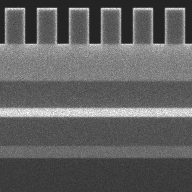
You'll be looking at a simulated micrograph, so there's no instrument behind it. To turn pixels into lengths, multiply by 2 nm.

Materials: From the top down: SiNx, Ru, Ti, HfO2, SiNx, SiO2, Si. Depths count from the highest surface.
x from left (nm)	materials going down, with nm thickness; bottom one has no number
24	SiNx 72, Ru 74, Ti 54, HfO2 18, SiNx 58, SiO2 24, Si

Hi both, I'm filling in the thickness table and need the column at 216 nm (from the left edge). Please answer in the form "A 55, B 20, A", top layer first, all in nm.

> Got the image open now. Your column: SiNx 72, Ru 74, Ti 54, HfO2 18, SiNx 58, SiO2 24, Si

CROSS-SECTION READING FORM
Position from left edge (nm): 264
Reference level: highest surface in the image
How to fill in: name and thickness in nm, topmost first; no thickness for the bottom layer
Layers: empty 72, Ru 74, Ti 54, HfO2 18, SiNx 58, SiO2 24, Si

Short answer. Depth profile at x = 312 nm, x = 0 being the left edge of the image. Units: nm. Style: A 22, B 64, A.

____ empty 72, Ru 74, Ti 54, HfO2 18, SiNx 58, SiO2 24, Si